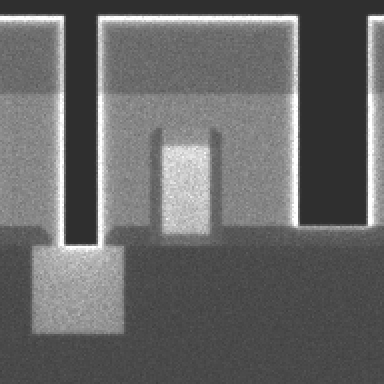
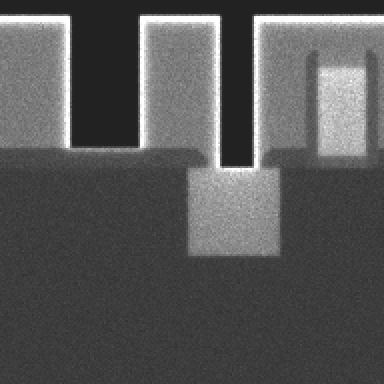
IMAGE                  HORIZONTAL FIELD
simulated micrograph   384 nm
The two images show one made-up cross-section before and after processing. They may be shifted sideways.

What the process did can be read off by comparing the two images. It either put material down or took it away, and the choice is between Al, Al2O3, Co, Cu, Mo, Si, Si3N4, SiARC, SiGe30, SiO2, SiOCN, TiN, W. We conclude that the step removed SiARC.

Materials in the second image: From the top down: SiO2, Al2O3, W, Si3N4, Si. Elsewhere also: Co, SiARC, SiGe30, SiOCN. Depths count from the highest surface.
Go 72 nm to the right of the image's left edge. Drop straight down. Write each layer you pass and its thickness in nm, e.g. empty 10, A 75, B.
empty 132, SiGe30 20, Si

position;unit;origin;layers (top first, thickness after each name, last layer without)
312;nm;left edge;SiO2 34, SiOCN 118, Si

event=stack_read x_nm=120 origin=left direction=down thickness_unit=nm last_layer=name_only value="empty 132, SiGe30 20, Si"